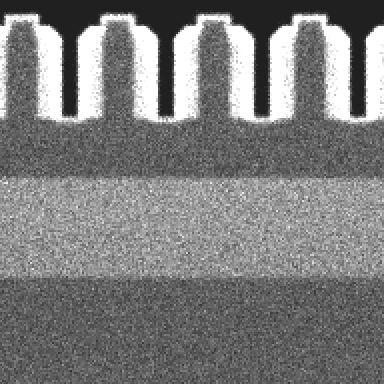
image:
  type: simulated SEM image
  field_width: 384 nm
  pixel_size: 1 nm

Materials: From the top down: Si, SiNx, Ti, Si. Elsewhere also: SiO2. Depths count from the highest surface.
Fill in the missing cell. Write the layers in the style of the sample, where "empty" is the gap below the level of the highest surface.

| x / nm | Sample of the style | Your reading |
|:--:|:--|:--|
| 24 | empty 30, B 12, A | Si 162, SiNx 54, Ti 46, Si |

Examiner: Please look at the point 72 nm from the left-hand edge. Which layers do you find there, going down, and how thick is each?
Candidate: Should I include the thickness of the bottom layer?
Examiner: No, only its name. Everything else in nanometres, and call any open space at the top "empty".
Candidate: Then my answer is empty 102, Si 60, SiNx 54, Ti 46, Si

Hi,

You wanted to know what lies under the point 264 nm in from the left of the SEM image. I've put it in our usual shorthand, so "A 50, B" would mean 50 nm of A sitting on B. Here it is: empty 102, Si 60, SiNx 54, Ti 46, Si